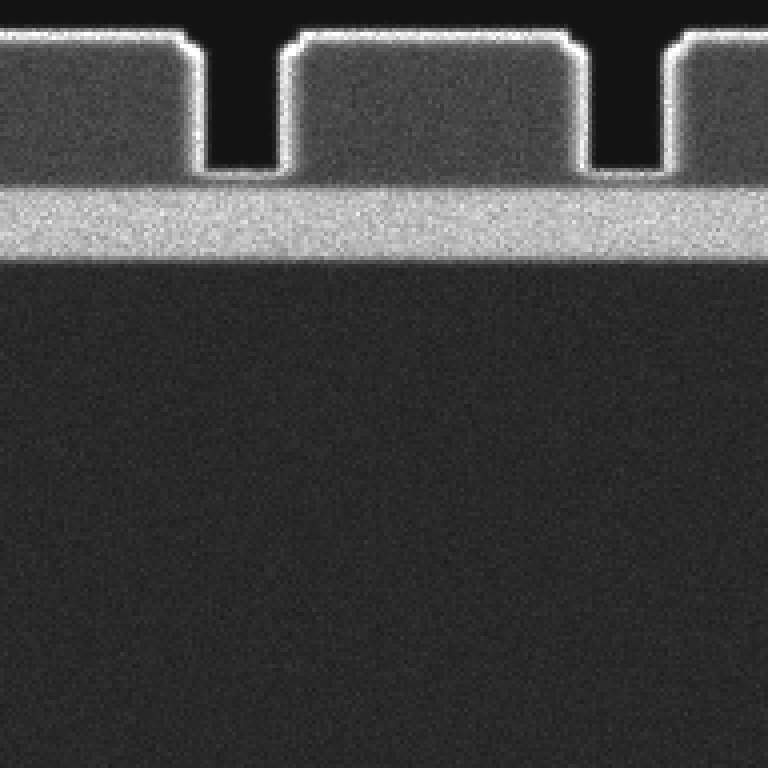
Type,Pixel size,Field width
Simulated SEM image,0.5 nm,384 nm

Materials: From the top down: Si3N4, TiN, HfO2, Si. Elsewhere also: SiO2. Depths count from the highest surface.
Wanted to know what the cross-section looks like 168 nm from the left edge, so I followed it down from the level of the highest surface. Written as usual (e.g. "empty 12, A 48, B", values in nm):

Si3N4 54, TiN 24, HfO2 36, Si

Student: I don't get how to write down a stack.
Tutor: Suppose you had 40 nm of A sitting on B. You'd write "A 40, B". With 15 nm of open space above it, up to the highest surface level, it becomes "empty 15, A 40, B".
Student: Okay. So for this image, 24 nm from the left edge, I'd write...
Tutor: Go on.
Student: Si3N4 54, TiN 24, HfO2 36, Si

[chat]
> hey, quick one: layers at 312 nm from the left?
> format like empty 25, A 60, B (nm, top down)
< empty 70, TiN 8, HfO2 36, Si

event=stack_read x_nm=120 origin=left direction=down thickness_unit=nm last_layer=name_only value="empty 70, TiN 8, HfO2 36, Si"